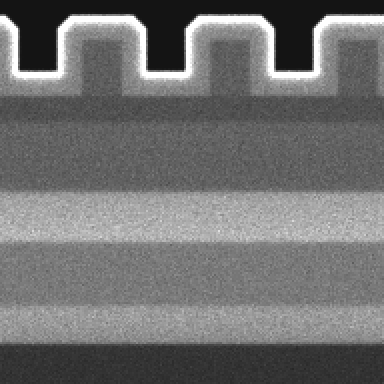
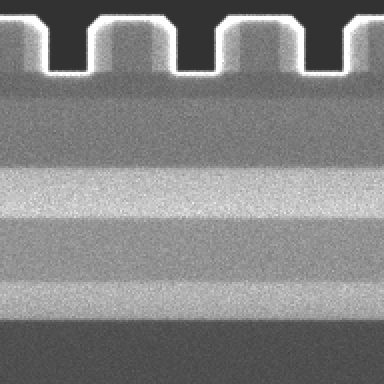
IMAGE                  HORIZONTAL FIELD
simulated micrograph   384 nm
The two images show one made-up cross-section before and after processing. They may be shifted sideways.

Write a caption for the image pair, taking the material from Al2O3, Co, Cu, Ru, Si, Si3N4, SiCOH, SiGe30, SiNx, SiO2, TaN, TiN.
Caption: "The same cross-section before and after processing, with Al2O3 removed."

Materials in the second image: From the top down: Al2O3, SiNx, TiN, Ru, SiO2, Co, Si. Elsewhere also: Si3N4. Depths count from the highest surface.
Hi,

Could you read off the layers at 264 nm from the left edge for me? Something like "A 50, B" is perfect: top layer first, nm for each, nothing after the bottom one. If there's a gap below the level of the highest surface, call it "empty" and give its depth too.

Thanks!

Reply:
Si3N4 56, SiNx 26, TiN 70, Ru 50, SiO2 64, Co 38, Si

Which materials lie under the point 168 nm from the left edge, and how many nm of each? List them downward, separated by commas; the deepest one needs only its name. empty 6, Al2O3 50, SiNx 26, TiN 70, Ru 50, SiO2 64, Co 38, Si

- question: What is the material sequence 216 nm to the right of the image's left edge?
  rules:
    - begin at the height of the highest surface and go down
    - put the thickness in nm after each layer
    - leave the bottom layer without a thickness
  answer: empty 12, Al2O3 44, SiNx 26, TiN 70, Ru 50, SiO2 64, Co 38, Si